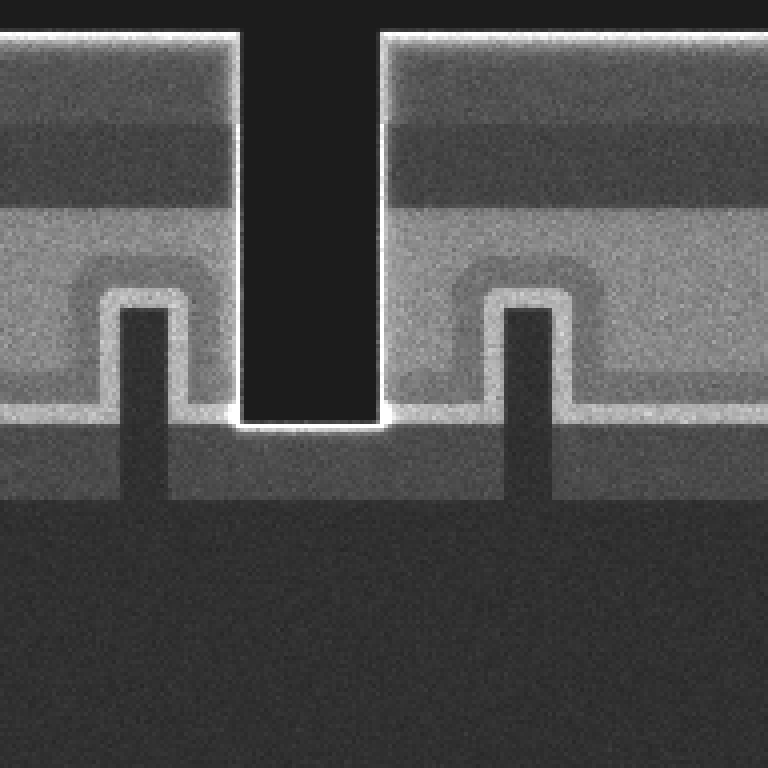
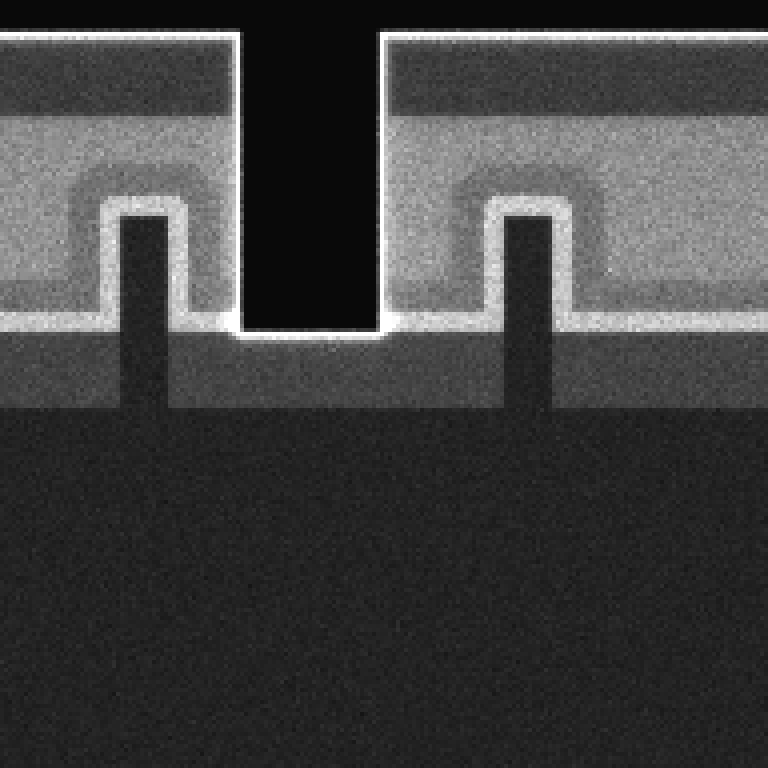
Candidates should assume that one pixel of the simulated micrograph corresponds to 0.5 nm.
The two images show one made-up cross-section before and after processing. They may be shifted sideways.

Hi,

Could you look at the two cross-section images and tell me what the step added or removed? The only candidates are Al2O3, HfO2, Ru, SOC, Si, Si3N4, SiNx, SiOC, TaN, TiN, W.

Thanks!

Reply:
removed SOC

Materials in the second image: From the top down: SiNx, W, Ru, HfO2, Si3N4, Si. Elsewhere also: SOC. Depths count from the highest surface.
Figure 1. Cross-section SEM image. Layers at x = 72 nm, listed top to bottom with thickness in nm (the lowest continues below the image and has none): SiNx 42, W 24, Ru 16, HfO2 10, Si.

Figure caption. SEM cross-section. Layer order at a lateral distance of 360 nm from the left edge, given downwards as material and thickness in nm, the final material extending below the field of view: SiNx 42, W 82, Ru 16, HfO2 10, Si3N4 38, Si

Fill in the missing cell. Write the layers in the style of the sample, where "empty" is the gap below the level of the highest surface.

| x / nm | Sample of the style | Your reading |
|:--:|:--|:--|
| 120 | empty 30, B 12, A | empty 150, Si3N4 38, Si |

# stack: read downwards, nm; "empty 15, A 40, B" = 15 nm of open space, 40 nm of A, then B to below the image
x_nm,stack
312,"SiNx 42, W 82, Ru 16, HfO2 10, Si3N4 38, Si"